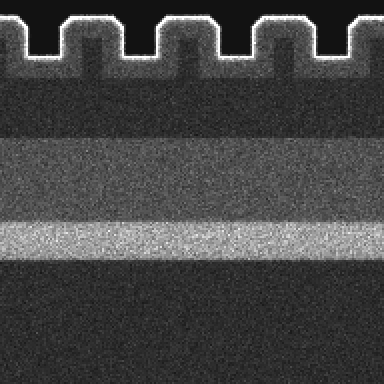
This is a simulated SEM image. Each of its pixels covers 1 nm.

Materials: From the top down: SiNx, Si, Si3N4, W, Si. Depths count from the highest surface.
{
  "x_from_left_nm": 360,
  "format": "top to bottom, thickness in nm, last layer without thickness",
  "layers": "SiNx 62, Si 60, Si3N4 84, W 38, Si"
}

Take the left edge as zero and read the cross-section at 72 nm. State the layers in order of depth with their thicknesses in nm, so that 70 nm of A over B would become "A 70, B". SiNx 62, Si 60, Si3N4 84, W 38, Si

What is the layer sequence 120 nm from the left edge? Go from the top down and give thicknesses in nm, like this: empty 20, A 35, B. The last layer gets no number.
empty 8, SiNx 54, Si 60, Si3N4 84, W 38, Si